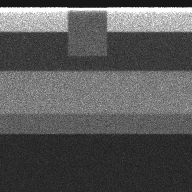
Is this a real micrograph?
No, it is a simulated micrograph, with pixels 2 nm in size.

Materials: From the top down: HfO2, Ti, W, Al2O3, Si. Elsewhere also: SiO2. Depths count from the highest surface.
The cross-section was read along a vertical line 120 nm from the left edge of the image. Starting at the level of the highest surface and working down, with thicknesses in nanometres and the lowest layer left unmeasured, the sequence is HfO2 48, Ti 78, W 86, Al2O3 40, Si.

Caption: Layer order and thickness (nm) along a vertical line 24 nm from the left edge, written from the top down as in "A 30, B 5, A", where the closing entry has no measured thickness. HfO2 48, Ti 78, W 86, Al2O3 40, Si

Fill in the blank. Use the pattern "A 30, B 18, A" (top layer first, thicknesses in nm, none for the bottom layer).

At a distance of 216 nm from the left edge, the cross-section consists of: HfO2 48, Ti 78, W 86, Al2O3 40, Si